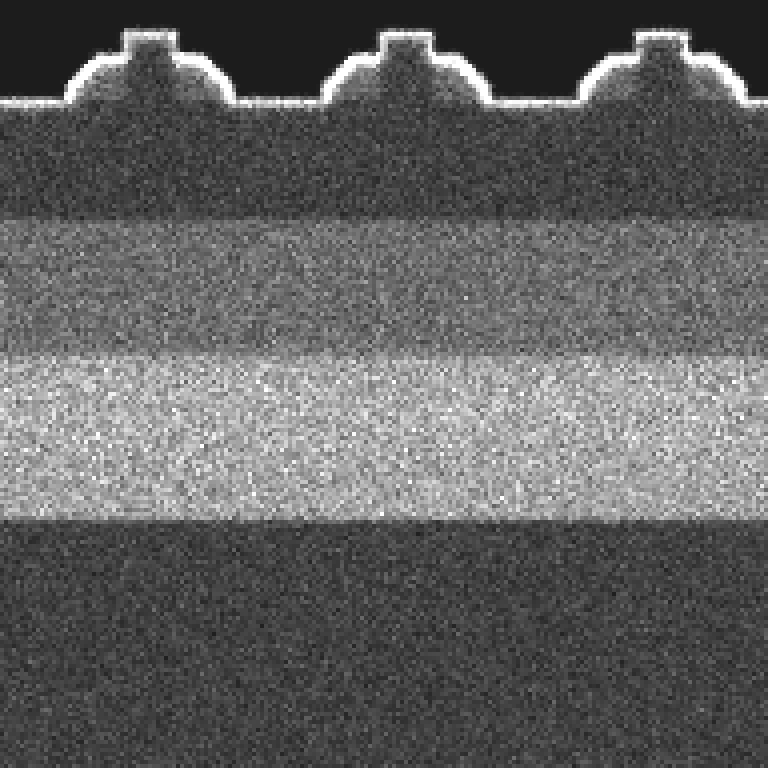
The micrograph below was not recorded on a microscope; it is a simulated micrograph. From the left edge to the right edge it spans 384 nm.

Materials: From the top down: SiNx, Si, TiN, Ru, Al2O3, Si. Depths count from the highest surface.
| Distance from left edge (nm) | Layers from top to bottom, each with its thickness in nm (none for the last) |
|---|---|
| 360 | empty 16, SiNx 18, Si 60, TiN 68, Ru 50, Al2O3 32, Si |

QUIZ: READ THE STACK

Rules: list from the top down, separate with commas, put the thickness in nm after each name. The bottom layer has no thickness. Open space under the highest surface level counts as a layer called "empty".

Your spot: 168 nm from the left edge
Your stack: empty 20, SiNx 14, Si 60, TiN 68, Ru 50, Al2O3 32, Si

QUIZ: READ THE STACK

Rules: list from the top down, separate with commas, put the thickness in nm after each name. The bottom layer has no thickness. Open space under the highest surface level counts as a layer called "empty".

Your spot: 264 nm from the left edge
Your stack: empty 34, Si 60, TiN 68, Ru 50, Al2O3 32, Si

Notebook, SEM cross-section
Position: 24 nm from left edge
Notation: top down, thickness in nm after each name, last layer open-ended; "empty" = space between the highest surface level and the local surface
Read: empty 34, Si 60, TiN 68, Ru 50, Al2O3 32, Si